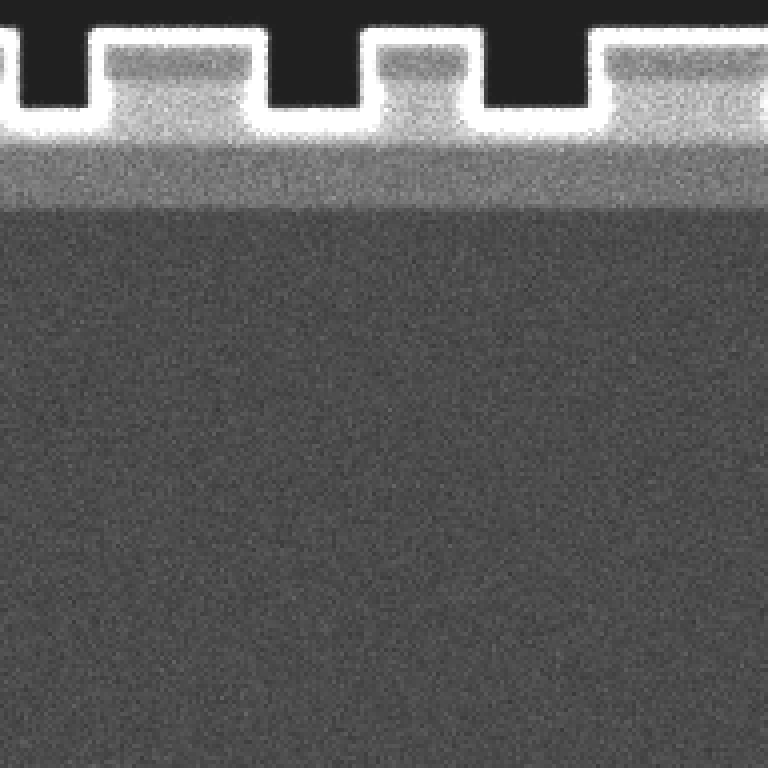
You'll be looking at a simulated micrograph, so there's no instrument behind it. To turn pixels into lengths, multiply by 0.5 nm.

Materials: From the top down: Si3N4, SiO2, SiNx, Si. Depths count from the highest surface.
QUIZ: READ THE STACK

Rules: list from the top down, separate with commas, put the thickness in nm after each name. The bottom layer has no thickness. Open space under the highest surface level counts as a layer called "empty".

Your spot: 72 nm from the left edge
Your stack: Si3N4 24, SiO2 32, SiNx 32, Si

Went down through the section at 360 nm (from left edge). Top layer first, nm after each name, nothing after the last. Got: Si3N4 24, SiO2 32, SiNx 32, Si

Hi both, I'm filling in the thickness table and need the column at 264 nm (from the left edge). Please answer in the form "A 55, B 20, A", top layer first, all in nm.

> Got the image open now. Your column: empty 40, SiO2 16, SiNx 32, Si